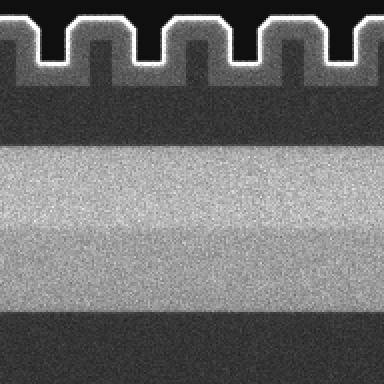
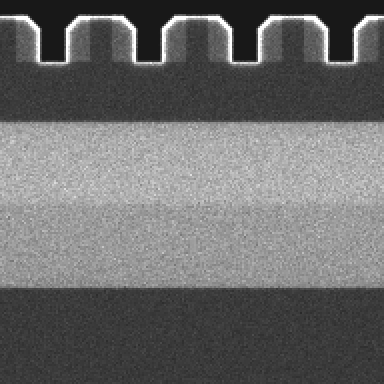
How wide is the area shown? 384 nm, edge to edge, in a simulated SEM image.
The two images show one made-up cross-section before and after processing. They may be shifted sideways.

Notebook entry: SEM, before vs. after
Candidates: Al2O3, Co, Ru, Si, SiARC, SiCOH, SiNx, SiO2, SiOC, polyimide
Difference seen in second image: SiNx removed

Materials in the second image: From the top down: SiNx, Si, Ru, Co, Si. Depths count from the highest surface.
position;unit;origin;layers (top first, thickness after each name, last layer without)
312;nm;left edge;SiNx 46, Si 60, Ru 82, Co 84, Si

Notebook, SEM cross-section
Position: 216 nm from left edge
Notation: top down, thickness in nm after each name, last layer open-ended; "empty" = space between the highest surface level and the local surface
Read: SiNx 46, Si 60, Ru 82, Co 84, Si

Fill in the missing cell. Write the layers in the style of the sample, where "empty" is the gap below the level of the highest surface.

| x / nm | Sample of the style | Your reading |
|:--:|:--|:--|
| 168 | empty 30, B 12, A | empty 6, SiNx 40, Si 60, Ru 82, Co 84, Si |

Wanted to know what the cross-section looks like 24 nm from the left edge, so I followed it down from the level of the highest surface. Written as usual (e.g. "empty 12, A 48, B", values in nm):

SiNx 46, Si 60, Ru 82, Co 84, Si